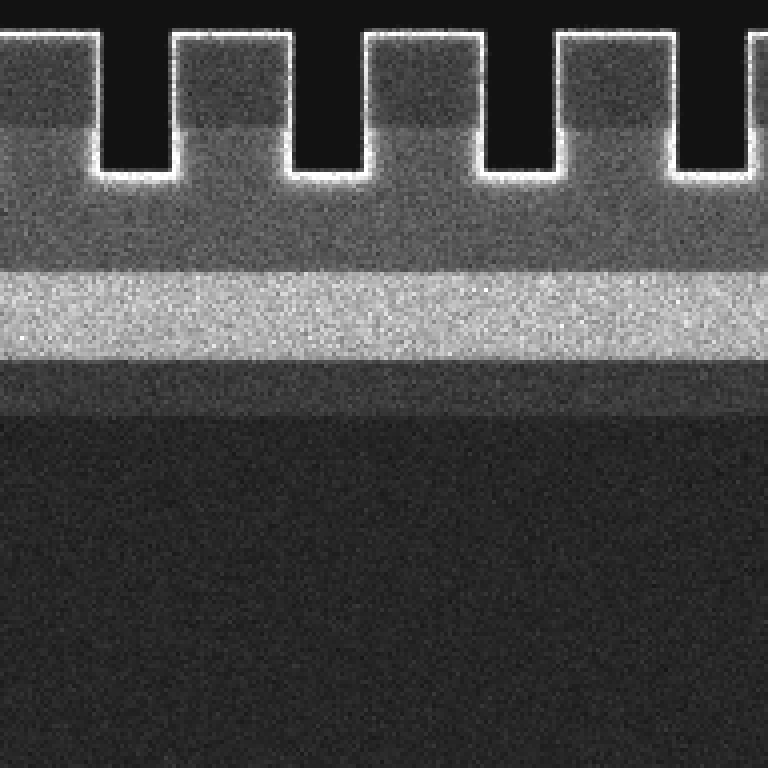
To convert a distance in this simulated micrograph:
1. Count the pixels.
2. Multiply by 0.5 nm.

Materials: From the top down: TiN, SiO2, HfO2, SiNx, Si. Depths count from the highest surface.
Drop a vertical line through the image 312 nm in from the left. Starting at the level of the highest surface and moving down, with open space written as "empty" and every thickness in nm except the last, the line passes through TiN 48, SiO2 72, HfO2 44, SiNx 28, Si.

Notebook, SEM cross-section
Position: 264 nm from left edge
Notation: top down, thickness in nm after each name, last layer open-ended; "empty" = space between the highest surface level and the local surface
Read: empty 70, SiO2 50, HfO2 44, SiNx 28, Si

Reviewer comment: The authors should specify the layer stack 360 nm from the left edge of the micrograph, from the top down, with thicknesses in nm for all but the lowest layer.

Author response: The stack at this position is empty 70, SiO2 50, HfO2 44, SiNx 28, Si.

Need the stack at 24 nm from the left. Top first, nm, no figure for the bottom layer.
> TiN 48, SiO2 72, HfO2 44, SiNx 28, Si